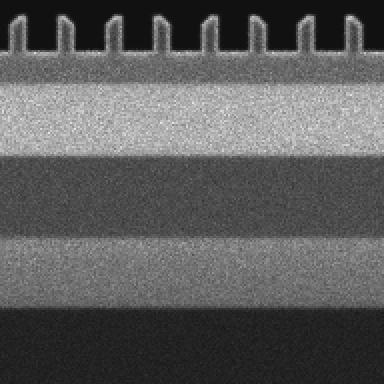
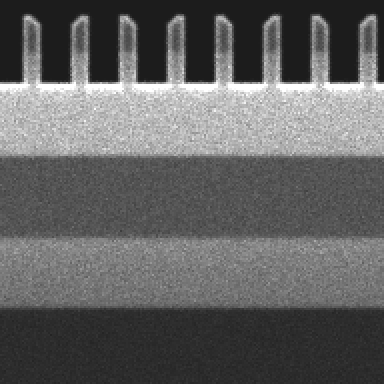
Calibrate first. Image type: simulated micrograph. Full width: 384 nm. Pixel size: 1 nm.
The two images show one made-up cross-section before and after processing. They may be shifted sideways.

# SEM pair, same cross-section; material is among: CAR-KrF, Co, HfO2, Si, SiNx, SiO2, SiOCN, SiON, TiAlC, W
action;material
removed;Co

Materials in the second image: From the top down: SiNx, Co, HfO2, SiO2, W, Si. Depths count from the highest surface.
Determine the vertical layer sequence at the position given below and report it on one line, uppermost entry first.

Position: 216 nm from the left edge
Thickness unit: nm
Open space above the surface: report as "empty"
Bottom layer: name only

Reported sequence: SiNx 36, Co 32, HfO2 72, SiO2 82, W 70, Si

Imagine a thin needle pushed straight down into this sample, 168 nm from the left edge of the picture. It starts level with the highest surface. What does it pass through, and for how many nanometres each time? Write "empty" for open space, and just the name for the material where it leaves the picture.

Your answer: empty 8, SiNx 28, Co 32, HfO2 72, SiO2 82, W 70, Si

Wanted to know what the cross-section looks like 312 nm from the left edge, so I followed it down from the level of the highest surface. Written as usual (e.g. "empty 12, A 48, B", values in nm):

SiNx 36, Co 32, HfO2 72, SiO2 82, W 70, Si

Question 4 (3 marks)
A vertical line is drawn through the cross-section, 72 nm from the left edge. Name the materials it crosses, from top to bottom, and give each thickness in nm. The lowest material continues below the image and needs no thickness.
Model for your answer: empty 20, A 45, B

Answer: empty 8, SiNx 28, Co 32, HfO2 72, SiO2 82, W 70, Si